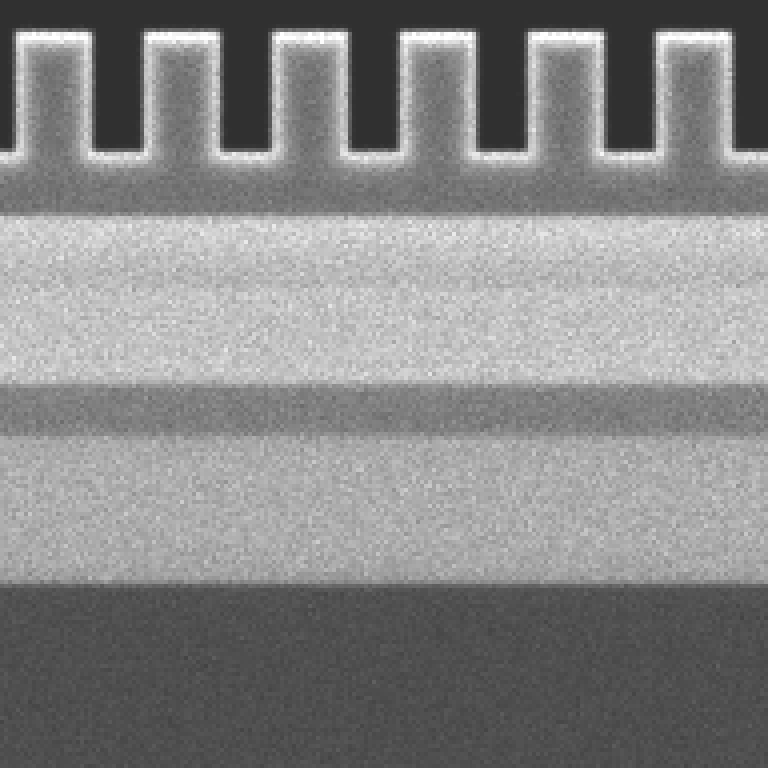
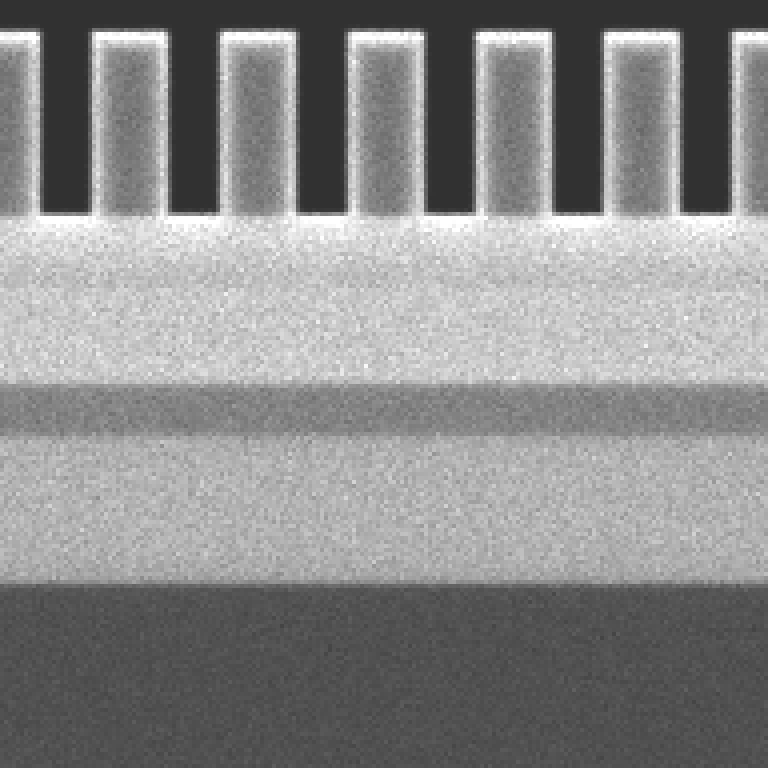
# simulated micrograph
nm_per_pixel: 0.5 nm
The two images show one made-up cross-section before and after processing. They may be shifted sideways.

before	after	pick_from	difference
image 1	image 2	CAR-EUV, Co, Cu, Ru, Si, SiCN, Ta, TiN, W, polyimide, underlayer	underlayer removed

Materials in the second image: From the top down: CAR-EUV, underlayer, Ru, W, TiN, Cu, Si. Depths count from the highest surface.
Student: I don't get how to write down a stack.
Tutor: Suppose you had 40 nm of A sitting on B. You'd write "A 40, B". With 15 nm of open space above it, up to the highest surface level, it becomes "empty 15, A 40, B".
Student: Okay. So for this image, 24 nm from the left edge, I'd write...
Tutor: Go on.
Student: empty 92, Ru 36, W 48, TiN 26, Cu 74, Si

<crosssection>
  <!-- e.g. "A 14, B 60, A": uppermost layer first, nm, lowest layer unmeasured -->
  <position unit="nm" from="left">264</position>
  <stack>CAR-EUV 60, underlayer 32, Ru 36, W 48, TiN 26, Cu 74, Si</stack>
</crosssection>